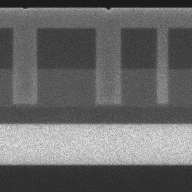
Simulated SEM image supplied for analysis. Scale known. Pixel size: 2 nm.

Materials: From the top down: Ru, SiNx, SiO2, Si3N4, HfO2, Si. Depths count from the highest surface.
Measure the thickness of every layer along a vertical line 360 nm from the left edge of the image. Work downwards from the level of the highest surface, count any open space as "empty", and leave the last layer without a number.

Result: Ru 40, SiNx 82, SiO2 76, Si3N4 34, HfO2 82, Si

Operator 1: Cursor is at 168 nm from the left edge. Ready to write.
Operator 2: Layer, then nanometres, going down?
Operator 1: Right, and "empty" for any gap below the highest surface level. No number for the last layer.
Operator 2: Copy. Ru 40, SiNx 82, SiO2 76, Si3N4 34, HfO2 82, Si